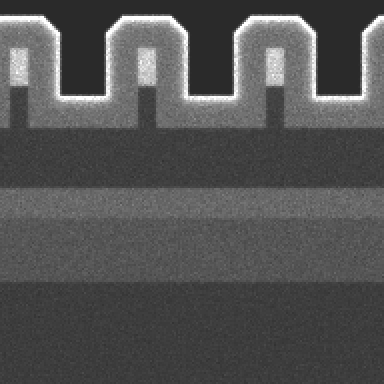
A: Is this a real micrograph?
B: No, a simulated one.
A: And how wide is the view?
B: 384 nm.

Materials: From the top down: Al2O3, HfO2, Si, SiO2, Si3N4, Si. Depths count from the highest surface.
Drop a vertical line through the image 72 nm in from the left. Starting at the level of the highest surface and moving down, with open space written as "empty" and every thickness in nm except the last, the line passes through empty 80, Al2O3 32, Si 60, SiO2 30, Si3N4 64, Si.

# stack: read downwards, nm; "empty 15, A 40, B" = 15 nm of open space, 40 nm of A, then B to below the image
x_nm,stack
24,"Al2O3 32, HfO2 38, Si 102, SiO2 30, Si3N4 64, Si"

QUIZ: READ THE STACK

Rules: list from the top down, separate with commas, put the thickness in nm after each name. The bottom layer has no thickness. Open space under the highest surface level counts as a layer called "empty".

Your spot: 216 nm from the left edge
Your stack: empty 80, Al2O3 32, Si 60, SiO2 30, Si3N4 64, Si